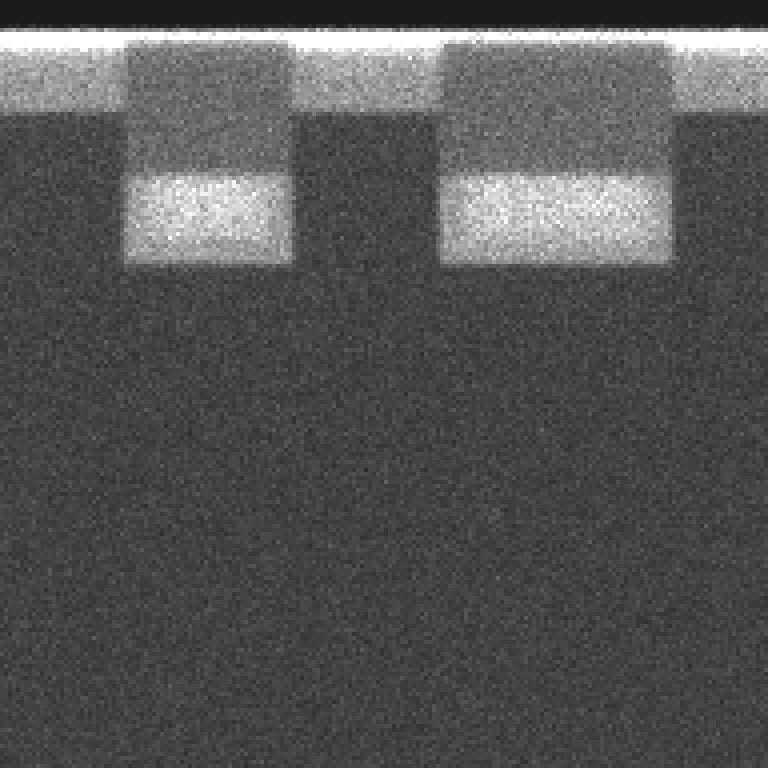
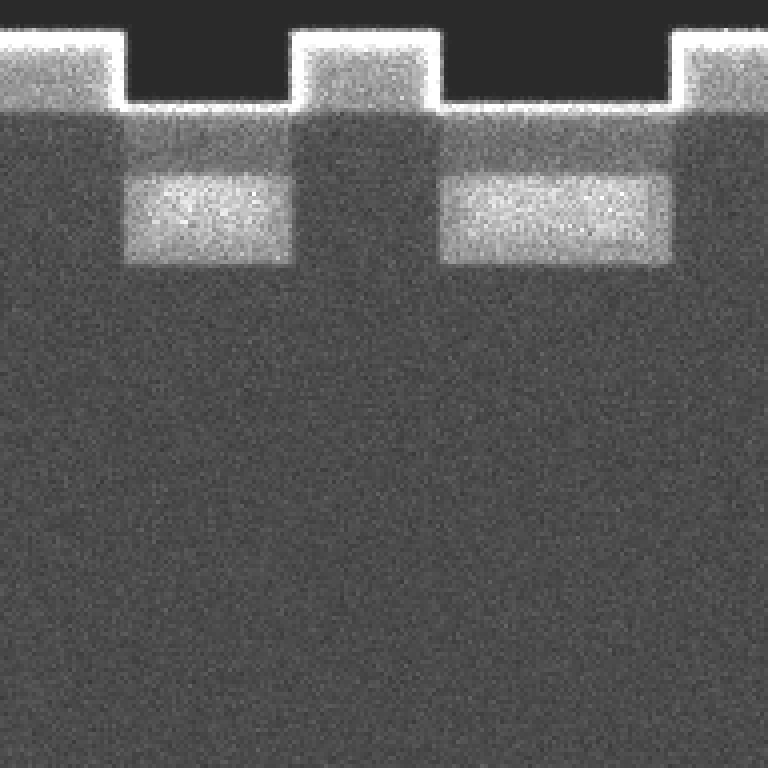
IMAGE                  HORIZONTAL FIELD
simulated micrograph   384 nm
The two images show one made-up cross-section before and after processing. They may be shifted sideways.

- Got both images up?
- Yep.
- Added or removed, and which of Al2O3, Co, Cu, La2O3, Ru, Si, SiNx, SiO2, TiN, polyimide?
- removed, SiNx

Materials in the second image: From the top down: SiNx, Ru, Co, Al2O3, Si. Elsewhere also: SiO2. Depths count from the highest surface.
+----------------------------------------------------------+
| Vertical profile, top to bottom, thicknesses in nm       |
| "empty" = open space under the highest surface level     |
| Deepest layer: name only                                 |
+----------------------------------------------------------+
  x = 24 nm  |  SiO2 40, Si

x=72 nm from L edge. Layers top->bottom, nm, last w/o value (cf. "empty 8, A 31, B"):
empty 36, SiNx 36, Al2O3 44, Si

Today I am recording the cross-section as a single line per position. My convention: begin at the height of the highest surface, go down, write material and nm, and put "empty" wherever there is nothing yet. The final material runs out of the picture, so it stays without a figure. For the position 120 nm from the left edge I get empty 36, SiNx 36, Ru 20, Co 12, Al2O3 12, Si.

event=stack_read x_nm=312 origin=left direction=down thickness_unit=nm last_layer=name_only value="empty 36, SiNx 36, Co 32, Al2O3 12, Si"